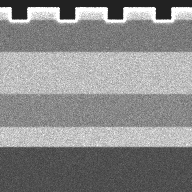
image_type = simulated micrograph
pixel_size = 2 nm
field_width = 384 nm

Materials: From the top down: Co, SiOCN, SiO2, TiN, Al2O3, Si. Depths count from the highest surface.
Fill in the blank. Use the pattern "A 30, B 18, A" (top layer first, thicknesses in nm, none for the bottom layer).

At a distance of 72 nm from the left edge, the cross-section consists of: Co 24, SiOCN 64, SiO2 84, TiN 66, Al2O3 40, Si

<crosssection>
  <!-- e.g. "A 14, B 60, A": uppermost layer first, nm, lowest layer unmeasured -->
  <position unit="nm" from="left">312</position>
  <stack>empty 24, SiOCN 64, SiO2 84, TiN 66, Al2O3 40, Si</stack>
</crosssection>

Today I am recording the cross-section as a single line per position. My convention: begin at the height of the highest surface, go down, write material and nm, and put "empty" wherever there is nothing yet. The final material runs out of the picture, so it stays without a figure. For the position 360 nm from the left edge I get Co 24, SiOCN 64, SiO2 84, TiN 66, Al2O3 40, Si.